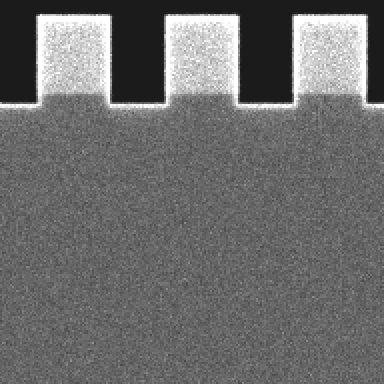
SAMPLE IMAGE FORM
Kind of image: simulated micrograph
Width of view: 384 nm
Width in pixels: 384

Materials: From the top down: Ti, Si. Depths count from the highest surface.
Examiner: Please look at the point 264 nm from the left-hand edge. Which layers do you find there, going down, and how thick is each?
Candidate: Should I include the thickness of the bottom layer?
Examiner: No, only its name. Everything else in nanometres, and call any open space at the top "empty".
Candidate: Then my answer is empty 88, Si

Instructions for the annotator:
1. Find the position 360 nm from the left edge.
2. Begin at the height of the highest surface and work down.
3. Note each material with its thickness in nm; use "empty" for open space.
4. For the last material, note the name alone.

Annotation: Ti 78, Si